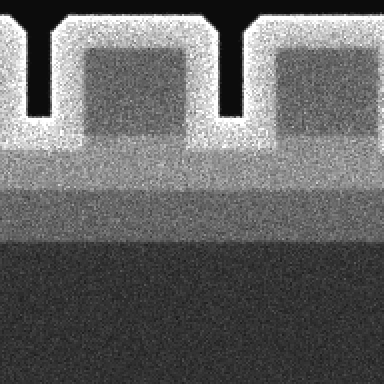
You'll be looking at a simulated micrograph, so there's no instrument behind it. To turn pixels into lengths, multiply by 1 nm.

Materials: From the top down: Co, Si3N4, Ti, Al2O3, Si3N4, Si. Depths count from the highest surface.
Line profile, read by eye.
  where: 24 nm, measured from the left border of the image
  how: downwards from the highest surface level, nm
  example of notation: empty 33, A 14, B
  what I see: empty 16, Co 118, Al2O3 40, Si3N4 52, Si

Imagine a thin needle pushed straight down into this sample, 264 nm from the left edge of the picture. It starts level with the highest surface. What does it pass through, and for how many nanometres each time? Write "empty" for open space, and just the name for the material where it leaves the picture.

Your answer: Co 134, Al2O3 40, Si3N4 52, Si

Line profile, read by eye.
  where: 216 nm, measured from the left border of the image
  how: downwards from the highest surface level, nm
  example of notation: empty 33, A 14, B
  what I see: empty 16, Co 118, Al2O3 40, Si3N4 52, Si